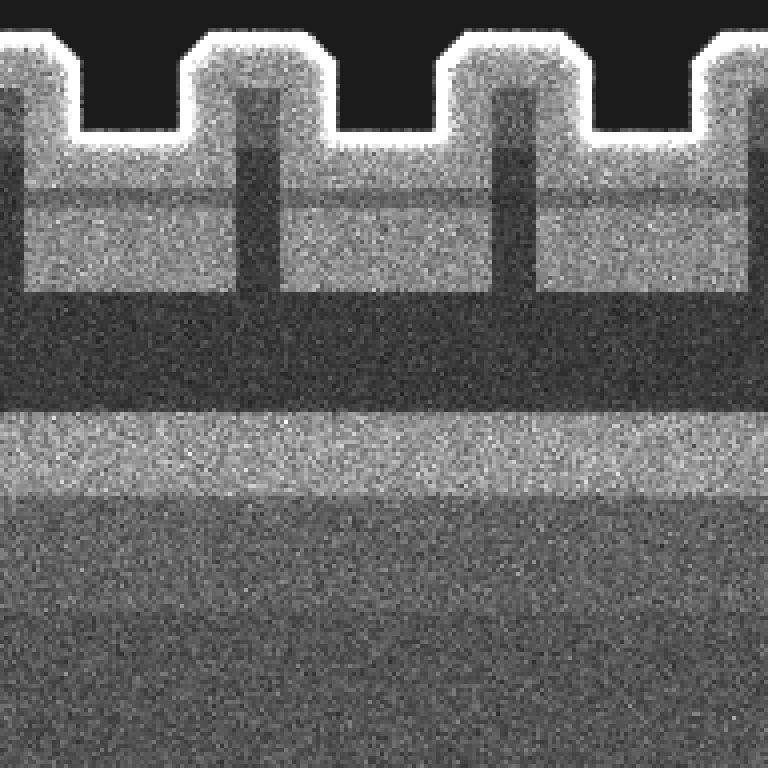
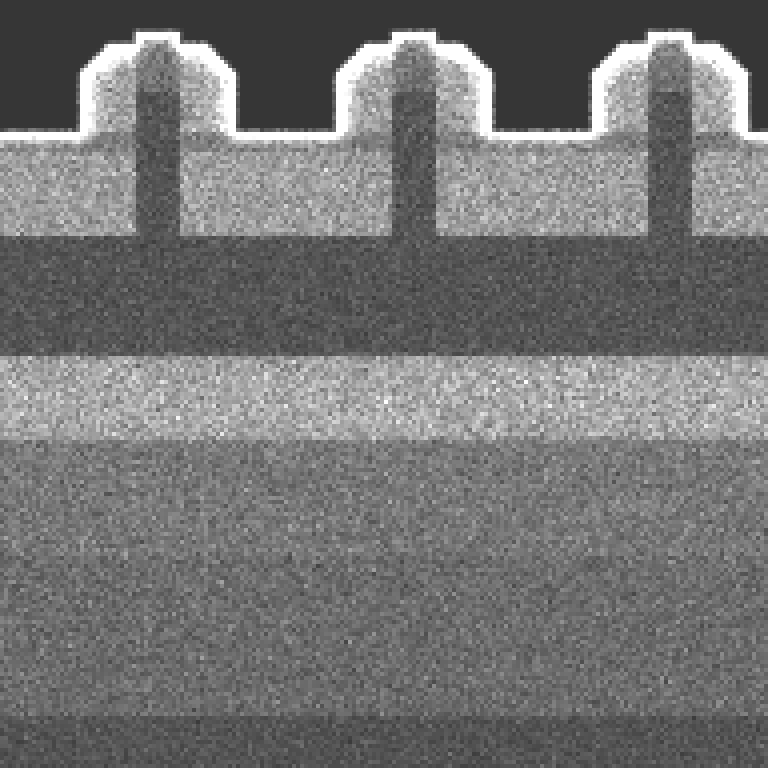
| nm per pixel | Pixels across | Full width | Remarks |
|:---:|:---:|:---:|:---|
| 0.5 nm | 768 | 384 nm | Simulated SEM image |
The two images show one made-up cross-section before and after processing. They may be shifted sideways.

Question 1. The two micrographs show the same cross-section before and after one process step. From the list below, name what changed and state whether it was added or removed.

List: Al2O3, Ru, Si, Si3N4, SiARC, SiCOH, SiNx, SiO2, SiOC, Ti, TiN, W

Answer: Al2O3, removed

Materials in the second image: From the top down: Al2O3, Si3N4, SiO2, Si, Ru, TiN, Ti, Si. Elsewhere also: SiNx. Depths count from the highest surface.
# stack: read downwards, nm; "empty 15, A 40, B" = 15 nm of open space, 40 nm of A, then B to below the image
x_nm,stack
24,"empty 50, Si3N4 10, SiO2 42, Si 60, Ru 42, TiN 58, Ti 80, Si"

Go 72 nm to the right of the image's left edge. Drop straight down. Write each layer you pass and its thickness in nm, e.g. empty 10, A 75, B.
SiNx 30, Si 132, Ru 42, TiN 58, Ti 80, Si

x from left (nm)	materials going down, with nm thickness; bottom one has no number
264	empty 50, Si3N4 10, SiO2 42, Si 60, Ru 42, TiN 58, Ti 80, Si